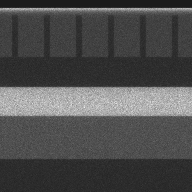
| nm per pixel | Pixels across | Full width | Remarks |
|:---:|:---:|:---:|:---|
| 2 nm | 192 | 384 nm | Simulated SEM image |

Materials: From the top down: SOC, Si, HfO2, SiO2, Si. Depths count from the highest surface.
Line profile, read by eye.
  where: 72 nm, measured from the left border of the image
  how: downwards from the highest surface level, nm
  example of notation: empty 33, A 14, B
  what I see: SOC 98, Si 60, HfO2 58, SiO2 86, Si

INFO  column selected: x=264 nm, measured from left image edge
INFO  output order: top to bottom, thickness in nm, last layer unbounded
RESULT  SOC 98, Si 60, HfO2 58, SiO2 86, Si